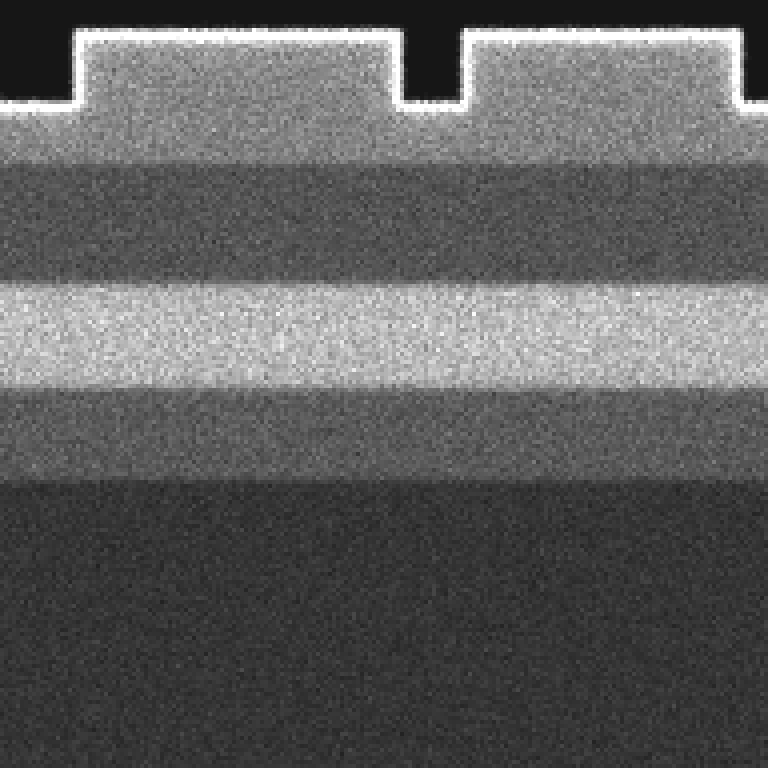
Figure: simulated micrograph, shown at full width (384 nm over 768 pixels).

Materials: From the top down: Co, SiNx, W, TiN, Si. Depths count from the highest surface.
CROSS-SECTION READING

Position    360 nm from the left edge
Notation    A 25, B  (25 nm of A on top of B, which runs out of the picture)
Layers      Co 66, SiNx 60, W 52, TiN 46, Si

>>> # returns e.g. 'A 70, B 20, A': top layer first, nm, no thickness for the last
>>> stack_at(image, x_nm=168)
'Co 66, SiNx 60, W 52, TiN 46, Si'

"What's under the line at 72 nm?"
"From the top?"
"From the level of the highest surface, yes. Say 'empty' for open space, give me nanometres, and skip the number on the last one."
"Co 66, SiNx 60, W 52, TiN 46, Si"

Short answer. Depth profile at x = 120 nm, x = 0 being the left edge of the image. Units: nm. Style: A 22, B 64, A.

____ Co 66, SiNx 60, W 52, TiN 46, Si